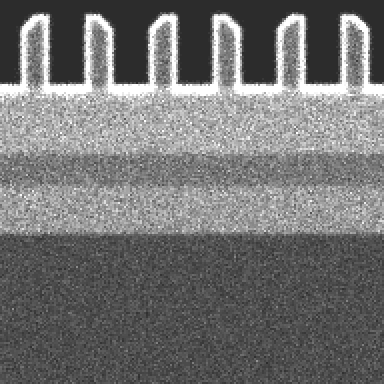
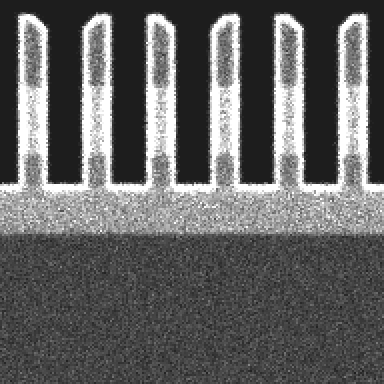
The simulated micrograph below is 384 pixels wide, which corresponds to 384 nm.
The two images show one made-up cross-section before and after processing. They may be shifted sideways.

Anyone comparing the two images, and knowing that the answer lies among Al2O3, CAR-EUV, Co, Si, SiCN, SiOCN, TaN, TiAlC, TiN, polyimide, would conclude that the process removed Al2O3 and TiN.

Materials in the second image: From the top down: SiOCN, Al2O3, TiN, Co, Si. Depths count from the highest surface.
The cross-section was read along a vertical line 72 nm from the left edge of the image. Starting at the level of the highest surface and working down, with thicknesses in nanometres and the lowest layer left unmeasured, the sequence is empty 170, Co 48, Si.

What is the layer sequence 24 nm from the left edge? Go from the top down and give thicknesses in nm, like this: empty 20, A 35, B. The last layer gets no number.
SiOCN 70, Al2O3 68, TiN 32, Co 48, Si